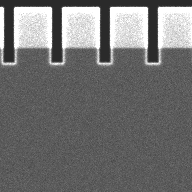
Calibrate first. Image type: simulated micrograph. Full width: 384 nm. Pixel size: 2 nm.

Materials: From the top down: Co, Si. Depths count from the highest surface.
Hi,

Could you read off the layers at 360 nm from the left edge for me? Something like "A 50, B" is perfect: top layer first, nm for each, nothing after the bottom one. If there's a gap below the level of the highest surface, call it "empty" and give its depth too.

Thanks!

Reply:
Co 80, Si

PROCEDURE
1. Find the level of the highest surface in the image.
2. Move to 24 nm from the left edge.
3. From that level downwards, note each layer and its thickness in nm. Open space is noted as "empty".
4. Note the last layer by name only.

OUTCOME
empty 110, Si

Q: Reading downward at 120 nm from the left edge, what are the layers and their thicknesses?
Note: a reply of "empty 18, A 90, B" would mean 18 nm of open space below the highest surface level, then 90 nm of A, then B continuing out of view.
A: empty 110, Si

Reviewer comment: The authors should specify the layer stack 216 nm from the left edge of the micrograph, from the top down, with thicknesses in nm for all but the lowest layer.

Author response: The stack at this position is empty 110, Si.